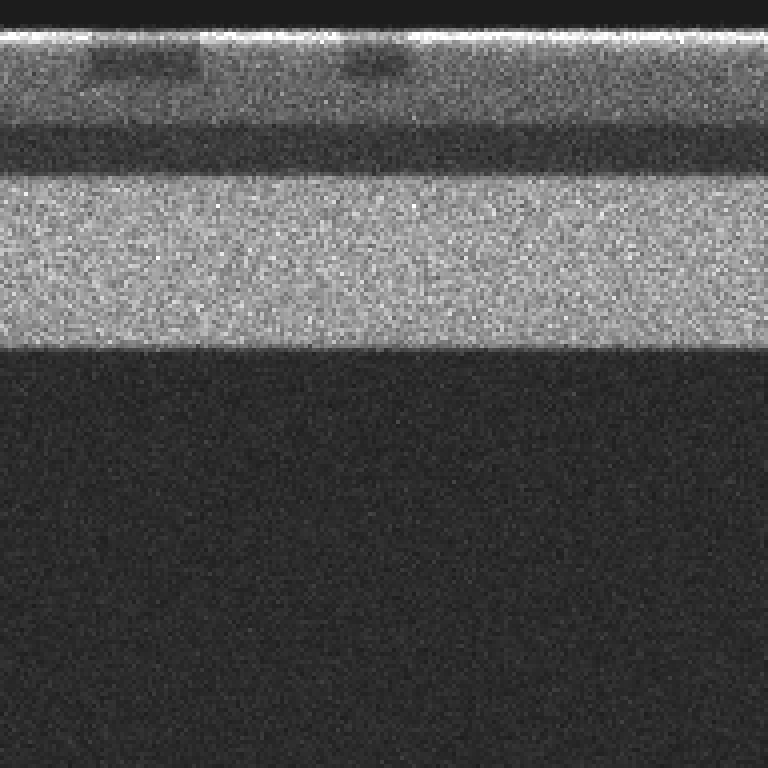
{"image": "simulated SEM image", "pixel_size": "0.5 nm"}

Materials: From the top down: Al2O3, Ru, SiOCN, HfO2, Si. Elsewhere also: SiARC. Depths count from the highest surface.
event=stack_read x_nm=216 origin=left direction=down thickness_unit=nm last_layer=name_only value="Al2O3 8, Ru 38, SiOCN 26, HfO2 86, Si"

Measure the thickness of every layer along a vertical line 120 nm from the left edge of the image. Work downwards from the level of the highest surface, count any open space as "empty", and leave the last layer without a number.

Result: Al2O3 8, Ru 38, SiOCN 26, HfO2 86, Si